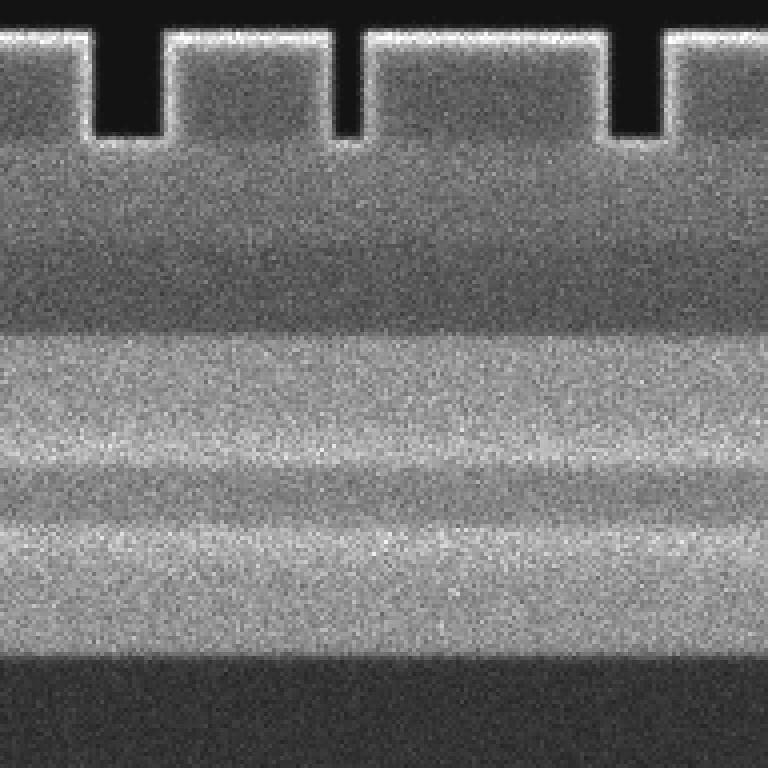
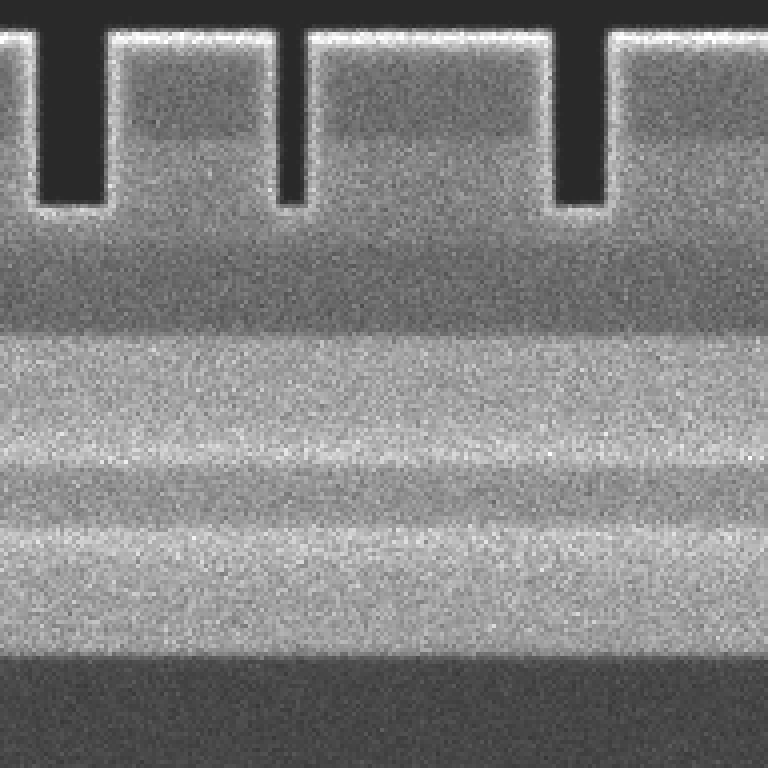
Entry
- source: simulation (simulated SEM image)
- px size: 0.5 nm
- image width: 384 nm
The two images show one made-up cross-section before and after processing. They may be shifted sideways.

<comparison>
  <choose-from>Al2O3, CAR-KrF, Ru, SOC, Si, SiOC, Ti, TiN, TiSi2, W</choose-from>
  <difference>TiN removed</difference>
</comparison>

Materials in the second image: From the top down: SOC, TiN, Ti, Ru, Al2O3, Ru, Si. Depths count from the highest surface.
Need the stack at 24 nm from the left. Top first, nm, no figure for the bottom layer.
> empty 88, TiN 18, Ti 46, Ru 64, Al2O3 32, Ru 64, Si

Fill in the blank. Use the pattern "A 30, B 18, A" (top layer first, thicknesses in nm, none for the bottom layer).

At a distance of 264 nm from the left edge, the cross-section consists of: SOC 54, TiN 52, Ti 46, Ru 64, Al2O3 32, Ru 64, Si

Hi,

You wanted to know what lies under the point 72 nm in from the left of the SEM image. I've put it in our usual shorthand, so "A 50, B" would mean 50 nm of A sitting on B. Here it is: SOC 54, TiN 52, Ti 46, Ru 64, Al2O3 32, Ru 64, Si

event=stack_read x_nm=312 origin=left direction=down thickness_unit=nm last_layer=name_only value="SOC 54, TiN 52, Ti 46, Ru 64, Al2O3 32, Ru 64, Si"